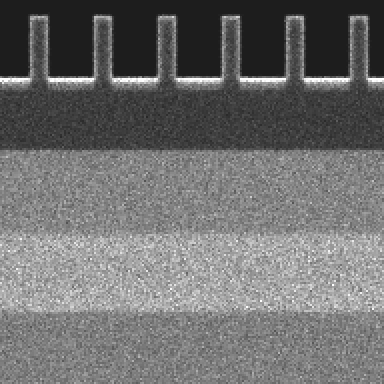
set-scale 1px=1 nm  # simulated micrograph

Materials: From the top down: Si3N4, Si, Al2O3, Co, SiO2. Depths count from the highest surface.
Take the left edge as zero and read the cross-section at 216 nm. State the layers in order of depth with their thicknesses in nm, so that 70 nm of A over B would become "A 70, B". empty 62, Si3N4 12, Si 60, Al2O3 84, Co 78, SiO2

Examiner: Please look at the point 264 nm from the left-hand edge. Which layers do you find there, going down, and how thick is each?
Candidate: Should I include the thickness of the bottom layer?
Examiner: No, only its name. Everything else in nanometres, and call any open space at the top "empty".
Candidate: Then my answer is empty 62, Si3N4 12, Si 60, Al2O3 84, Co 78, SiO2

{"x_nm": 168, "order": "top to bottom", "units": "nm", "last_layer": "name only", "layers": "Si 134, Al2O3 84, Co 78, SiO2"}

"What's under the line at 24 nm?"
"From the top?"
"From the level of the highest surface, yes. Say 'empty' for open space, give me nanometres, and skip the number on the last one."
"empty 62, Si3N4 12, Si 60, Al2O3 84, Co 78, SiO2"